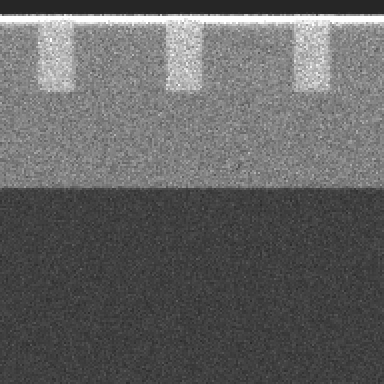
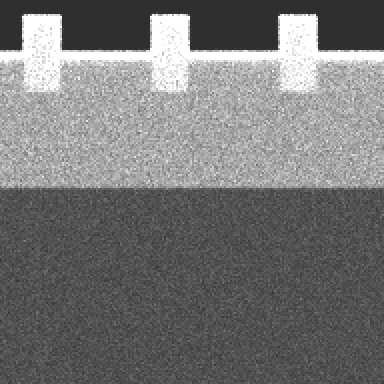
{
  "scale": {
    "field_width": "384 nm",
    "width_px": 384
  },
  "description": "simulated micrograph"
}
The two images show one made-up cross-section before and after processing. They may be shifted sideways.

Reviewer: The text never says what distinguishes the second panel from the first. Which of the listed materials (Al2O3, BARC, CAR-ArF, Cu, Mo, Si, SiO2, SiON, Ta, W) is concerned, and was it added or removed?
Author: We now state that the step removed Al2O3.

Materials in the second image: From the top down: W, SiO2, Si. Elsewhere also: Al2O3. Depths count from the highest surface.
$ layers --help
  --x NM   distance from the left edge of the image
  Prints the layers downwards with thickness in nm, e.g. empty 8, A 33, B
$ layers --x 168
W 76, SiO2 96, Si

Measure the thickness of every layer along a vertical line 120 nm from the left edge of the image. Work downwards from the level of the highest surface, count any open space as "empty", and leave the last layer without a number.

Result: empty 36, Al2O3 40, SiO2 96, Si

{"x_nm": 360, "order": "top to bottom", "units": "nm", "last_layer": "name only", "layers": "empty 36, Al2O3 40, SiO2 96, Si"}